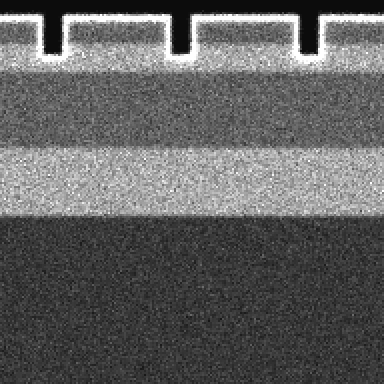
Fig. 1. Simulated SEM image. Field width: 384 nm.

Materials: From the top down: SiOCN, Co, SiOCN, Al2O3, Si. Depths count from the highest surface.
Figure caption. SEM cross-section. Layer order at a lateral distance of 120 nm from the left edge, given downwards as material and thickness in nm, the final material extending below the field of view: SiOCN 28, Co 28, SiOCN 76, Al2O3 68, Si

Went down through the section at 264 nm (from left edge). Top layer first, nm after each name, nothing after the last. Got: SiOCN 28, Co 28, SiOCN 76, Al2O3 68, Si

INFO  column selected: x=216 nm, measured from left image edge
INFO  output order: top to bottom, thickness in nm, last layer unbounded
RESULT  SiOCN 28, Co 28, SiOCN 76, Al2O3 68, Si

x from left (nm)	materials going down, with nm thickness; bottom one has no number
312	empty 40, Co 16, SiOCN 76, Al2O3 68, Si